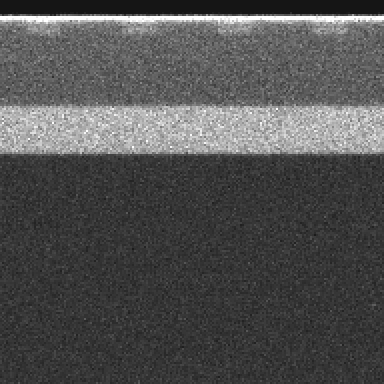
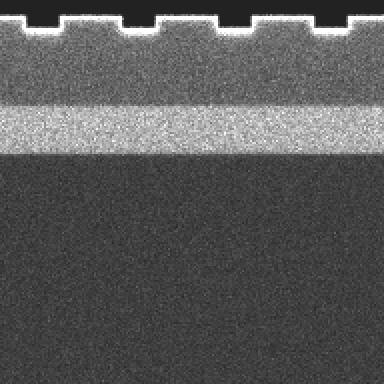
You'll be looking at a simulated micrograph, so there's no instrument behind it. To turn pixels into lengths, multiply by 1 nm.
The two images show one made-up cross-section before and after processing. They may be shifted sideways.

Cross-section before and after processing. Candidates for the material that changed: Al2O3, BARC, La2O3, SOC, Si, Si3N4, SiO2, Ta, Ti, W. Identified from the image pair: SOC (removed).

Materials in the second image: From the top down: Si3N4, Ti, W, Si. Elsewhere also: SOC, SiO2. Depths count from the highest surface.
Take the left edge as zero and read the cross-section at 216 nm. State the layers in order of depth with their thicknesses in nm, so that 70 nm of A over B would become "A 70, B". Si3N4 44, Ti 46, W 48, Si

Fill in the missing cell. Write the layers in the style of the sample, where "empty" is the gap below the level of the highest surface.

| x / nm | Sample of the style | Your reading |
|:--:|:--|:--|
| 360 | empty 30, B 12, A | Si3N4 44, Ti 46, W 48, Si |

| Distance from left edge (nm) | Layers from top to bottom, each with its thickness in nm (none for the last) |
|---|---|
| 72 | Si3N4 44, Ti 46, W 48, Si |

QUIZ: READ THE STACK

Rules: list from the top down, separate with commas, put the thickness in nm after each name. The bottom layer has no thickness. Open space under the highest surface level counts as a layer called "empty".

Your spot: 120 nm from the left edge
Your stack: Si3N4 44, Ti 46, W 48, Si